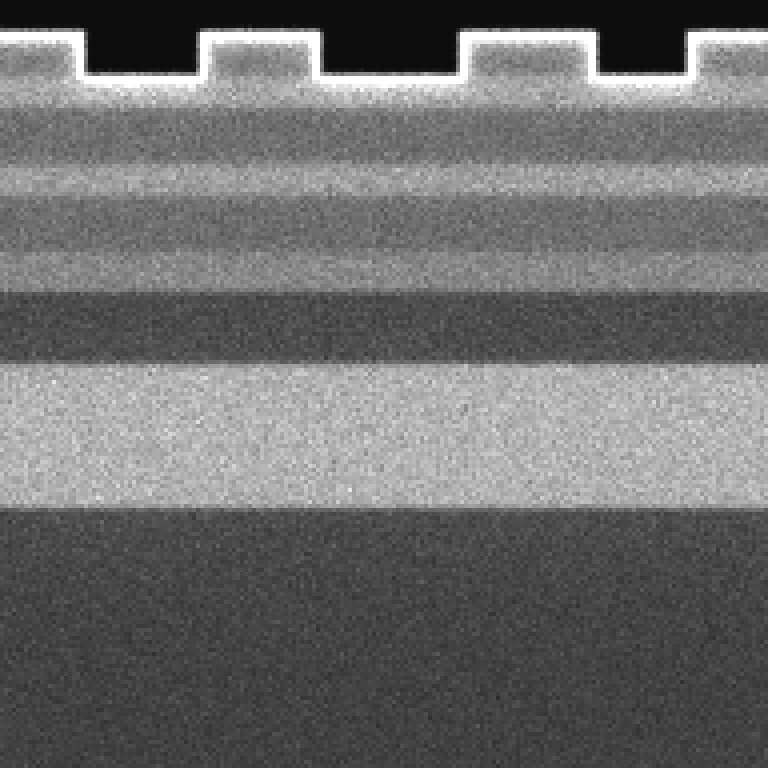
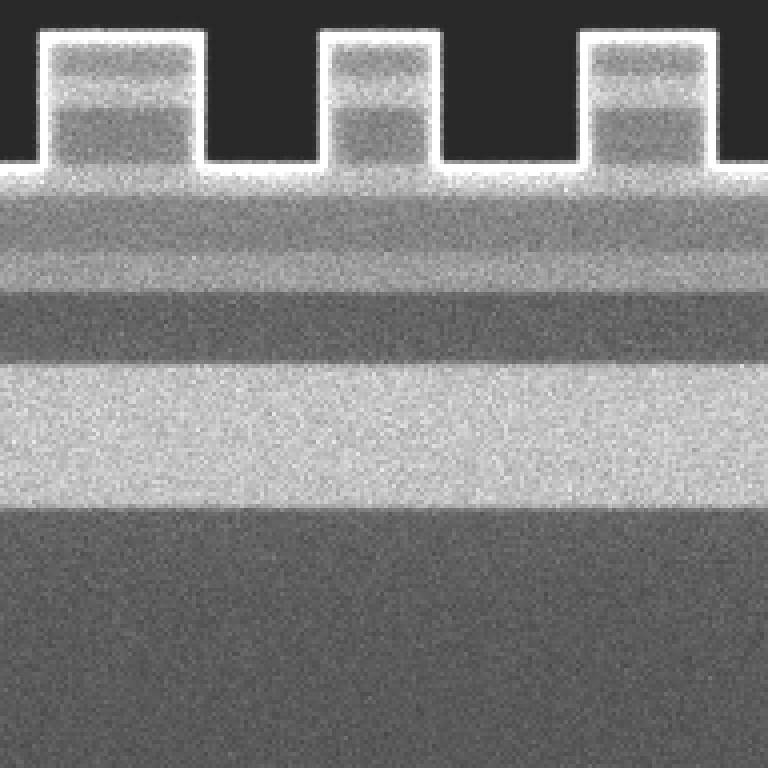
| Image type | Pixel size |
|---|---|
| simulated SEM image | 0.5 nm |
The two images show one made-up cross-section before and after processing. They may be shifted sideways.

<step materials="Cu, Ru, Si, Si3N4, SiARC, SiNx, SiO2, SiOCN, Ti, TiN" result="removed SiOCN and TiN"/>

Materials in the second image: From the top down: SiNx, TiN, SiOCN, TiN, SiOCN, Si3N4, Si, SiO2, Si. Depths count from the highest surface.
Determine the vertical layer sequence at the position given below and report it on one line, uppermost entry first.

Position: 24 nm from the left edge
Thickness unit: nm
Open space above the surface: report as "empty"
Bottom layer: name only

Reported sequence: SiNx 22, TiN 16, SiOCN 28, TiN 16, SiOCN 28, Si3N4 20, Si 36, SiO2 72, Si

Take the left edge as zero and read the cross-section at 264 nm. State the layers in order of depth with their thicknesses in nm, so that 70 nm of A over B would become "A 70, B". empty 66, TiN 16, SiOCN 28, Si3N4 20, Si 36, SiO2 72, Si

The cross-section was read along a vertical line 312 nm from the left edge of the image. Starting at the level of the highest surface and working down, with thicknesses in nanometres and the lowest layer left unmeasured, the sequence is SiNx 22, TiN 16, SiOCN 28, TiN 16, SiOCN 28, Si3N4 20, Si 36, SiO2 72, Si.